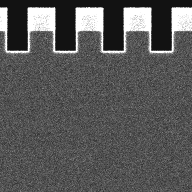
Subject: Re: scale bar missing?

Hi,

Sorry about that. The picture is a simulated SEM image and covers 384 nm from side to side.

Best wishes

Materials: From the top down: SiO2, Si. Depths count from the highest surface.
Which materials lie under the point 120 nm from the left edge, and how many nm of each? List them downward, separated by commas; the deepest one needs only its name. empty 86, Si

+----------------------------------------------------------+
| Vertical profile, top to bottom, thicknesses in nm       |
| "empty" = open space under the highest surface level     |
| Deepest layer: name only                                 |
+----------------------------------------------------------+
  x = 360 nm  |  SiO2 46, Si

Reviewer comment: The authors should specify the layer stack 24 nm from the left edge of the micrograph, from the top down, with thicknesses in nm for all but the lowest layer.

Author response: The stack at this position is empty 86, Si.